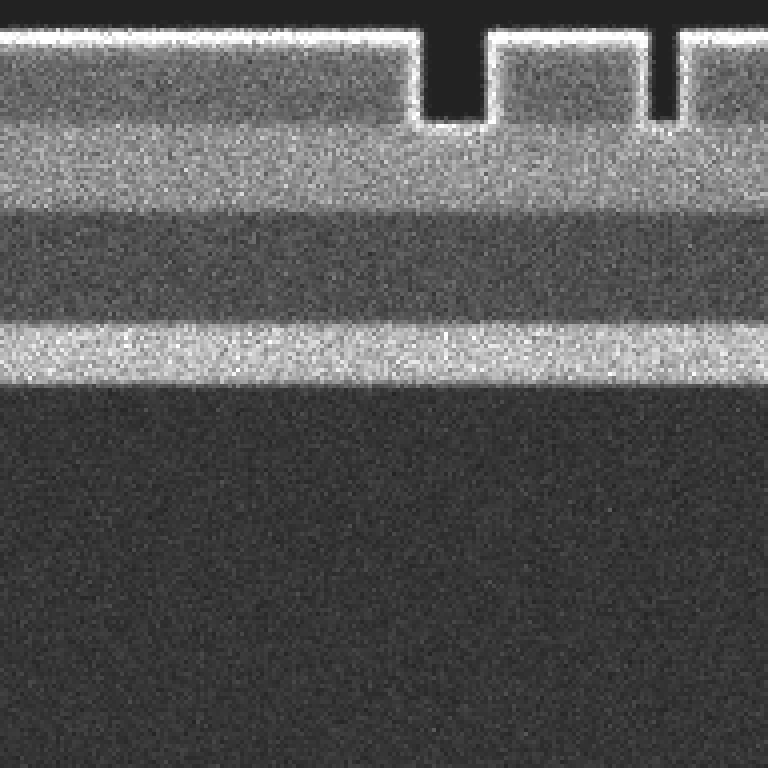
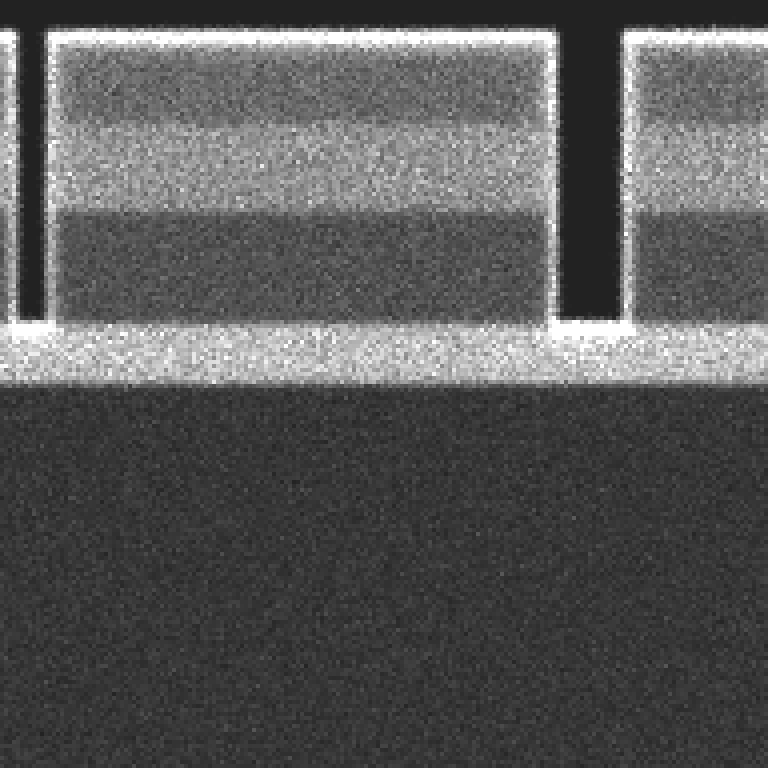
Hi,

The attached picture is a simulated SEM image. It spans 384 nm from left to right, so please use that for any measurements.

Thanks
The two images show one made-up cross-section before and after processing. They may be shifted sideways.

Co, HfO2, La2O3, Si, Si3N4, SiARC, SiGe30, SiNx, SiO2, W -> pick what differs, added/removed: Si3N4 and W removed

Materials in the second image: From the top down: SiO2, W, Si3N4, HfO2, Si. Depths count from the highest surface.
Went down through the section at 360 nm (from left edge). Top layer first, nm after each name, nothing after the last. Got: SiO2 46, W 44, Si3N4 56, HfO2 30, Si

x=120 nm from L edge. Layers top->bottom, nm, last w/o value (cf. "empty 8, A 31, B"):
SiO2 46, W 44, Si3N4 56, HfO2 30, Si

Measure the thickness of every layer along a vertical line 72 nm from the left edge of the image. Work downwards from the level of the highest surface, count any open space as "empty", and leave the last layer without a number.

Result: SiO2 46, W 44, Si3N4 56, HfO2 30, Si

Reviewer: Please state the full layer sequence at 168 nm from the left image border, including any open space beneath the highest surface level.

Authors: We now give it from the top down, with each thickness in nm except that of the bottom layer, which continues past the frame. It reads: SiO2 46, W 44, Si3N4 56, HfO2 30, Si